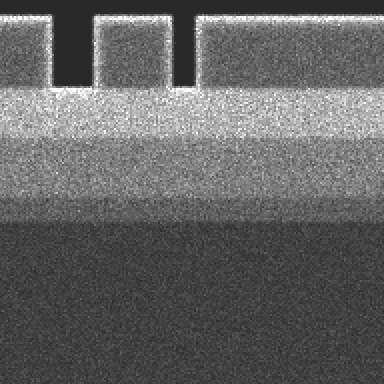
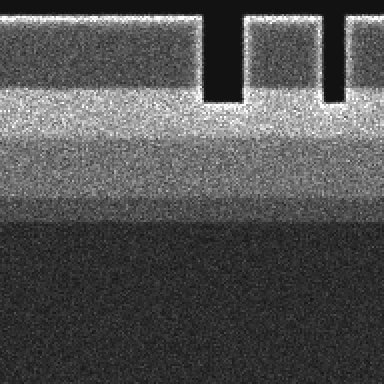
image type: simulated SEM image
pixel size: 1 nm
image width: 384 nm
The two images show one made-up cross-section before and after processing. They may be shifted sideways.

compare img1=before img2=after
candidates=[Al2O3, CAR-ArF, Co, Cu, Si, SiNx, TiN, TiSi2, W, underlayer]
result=removed:W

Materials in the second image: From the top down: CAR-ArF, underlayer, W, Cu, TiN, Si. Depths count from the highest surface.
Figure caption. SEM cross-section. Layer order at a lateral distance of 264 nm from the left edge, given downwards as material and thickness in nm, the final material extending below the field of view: CAR-ArF 40, underlayer 32, W 50, Cu 60, TiN 24, Si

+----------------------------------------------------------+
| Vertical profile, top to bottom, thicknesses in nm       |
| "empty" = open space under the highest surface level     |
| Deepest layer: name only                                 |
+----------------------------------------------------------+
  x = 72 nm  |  CAR-ArF 40, underlayer 32, W 50, Cu 60, TiN 24, Si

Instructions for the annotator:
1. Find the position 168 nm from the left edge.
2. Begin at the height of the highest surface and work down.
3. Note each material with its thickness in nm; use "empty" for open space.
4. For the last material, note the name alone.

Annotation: CAR-ArF 40, underlayer 32, W 50, Cu 60, TiN 24, Si